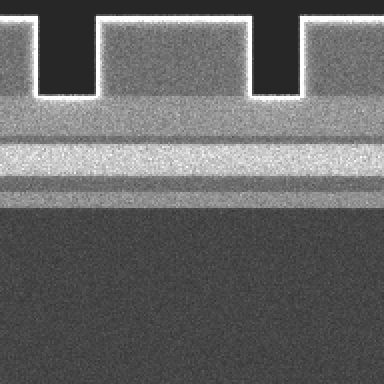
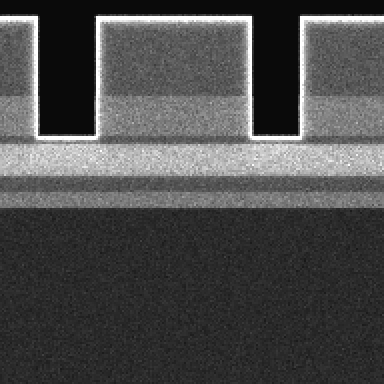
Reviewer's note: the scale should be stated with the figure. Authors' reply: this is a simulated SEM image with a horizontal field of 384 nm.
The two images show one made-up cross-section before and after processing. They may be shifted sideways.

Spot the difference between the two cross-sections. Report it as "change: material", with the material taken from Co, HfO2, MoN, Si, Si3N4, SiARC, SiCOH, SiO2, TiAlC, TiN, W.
removed: Co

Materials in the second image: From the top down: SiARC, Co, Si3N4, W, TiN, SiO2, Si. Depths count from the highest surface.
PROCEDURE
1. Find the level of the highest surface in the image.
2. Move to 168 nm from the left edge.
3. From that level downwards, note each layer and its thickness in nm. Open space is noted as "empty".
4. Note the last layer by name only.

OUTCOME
SiARC 80, Co 40, Si3N4 8, W 32, TiN 16, SiO2 16, Si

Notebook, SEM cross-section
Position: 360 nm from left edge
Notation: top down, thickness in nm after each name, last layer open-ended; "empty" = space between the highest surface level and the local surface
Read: SiARC 80, Co 40, Si3N4 8, W 32, TiN 16, SiO2 16, Si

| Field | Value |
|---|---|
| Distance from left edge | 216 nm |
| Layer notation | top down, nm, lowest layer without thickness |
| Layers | SiARC 80, Co 40, Si3N4 8, W 32, TiN 16, SiO2 16, Si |